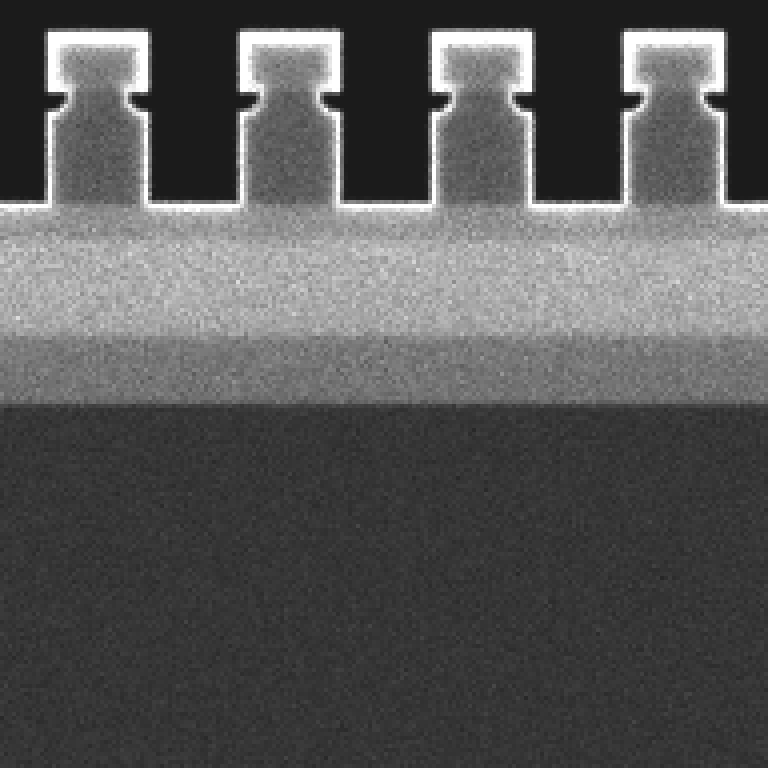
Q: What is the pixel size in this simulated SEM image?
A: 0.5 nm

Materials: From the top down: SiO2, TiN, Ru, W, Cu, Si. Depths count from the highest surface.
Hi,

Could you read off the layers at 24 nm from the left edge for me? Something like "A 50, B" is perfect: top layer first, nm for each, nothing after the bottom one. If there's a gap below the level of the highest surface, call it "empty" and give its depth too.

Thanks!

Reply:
SiO2 30, empty 10, TiN 46, Ru 18, W 48, Cu 34, Si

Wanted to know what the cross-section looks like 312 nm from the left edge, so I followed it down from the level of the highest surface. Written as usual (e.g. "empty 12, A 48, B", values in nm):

SiO2 30, empty 10, TiN 46, Ru 18, W 48, Cu 34, Si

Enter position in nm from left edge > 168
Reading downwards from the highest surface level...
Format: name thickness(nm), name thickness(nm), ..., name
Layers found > SiO2 30, empty 10, TiN 46, Ru 18, W 48, Cu 34, Si